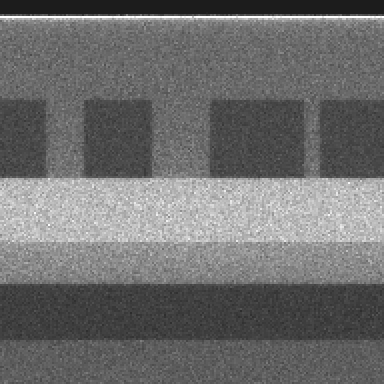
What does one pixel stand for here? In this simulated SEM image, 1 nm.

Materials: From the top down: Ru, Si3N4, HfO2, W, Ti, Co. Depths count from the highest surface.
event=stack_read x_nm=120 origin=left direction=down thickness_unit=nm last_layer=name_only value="Ru 84, Si3N4 78, HfO2 64, W 42, Ti 56, Co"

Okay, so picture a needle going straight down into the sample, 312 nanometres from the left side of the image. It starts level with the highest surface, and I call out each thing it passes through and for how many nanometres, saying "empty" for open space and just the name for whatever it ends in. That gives Ru 162, HfO2 64, W 42, Ti 56, Co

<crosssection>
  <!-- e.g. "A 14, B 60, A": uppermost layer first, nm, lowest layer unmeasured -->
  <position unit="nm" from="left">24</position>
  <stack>Ru 84, Si3N4 78, HfO2 64, W 42, Ti 56, Co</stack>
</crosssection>